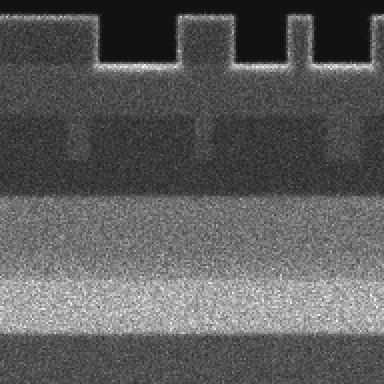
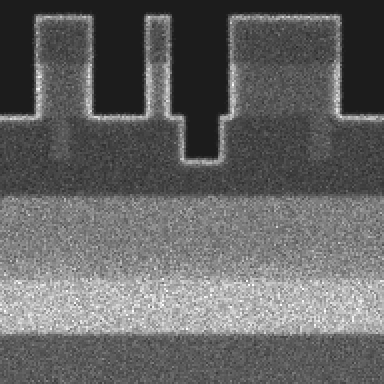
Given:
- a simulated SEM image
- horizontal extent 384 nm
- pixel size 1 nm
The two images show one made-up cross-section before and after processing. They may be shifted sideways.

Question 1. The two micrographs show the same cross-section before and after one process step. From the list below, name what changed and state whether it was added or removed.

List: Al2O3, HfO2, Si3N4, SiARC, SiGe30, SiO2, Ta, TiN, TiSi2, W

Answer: SiO2, removed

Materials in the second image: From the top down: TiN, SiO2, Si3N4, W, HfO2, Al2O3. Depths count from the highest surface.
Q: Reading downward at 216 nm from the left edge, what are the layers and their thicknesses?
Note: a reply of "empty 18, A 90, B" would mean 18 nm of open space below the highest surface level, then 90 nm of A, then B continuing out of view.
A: empty 144, Si3N4 36, W 84, HfO2 54, Al2O3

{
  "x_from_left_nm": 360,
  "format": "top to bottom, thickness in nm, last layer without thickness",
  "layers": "empty 100, Si3N4 80, W 84, HfO2 54, Al2O3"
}